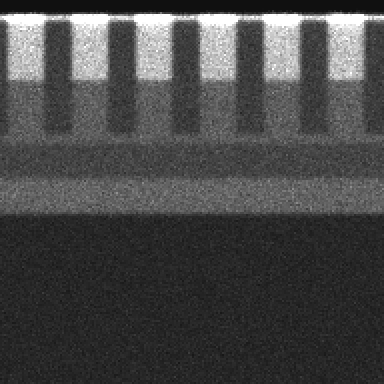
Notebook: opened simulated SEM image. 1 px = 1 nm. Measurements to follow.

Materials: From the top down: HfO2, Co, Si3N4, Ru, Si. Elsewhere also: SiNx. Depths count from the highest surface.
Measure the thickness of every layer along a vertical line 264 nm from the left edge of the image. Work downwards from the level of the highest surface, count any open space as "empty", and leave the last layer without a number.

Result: HfO2 64, Co 64, Si3N4 34, Ru 36, Si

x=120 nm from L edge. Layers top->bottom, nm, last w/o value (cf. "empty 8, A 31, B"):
SiNx 118, Co 10, Si3N4 34, Ru 36, Si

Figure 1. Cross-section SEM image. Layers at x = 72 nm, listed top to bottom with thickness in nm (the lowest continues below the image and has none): HfO2 64, Co 64, Si3N4 34, Ru 36, Si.